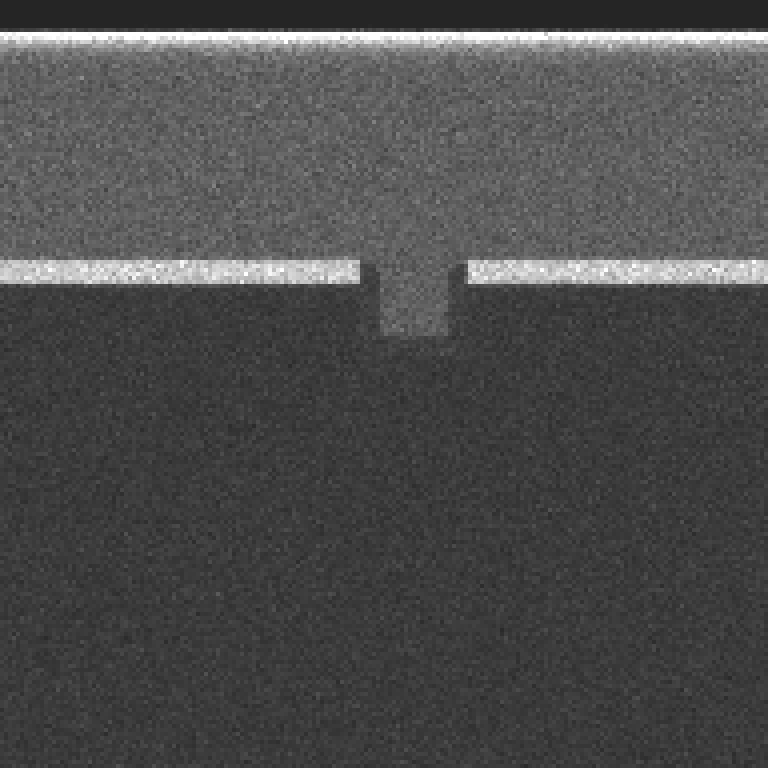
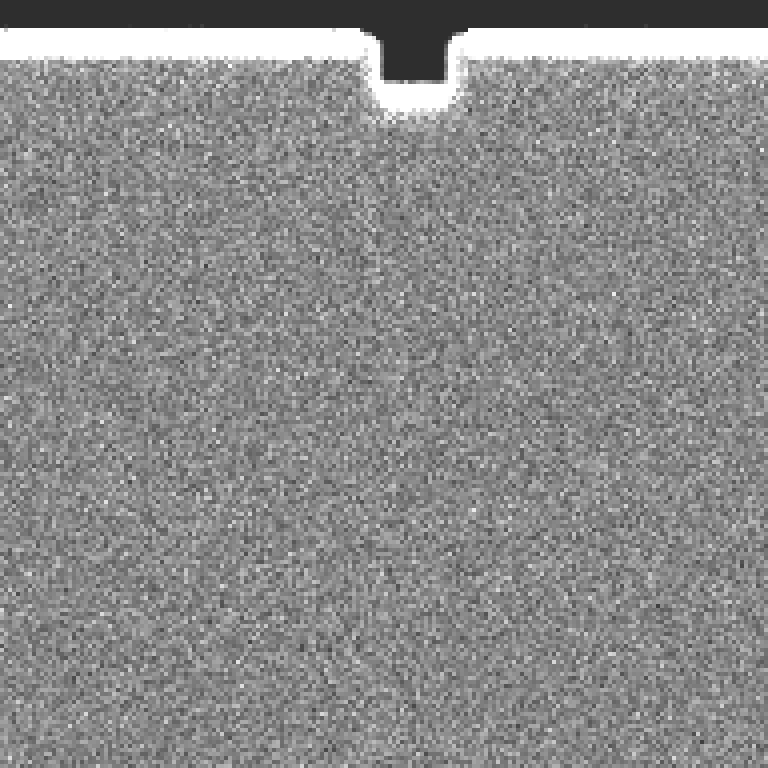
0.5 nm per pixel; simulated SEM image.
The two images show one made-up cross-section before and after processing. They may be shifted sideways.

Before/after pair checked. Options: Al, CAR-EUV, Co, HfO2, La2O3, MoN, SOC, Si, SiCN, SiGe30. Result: removed SOC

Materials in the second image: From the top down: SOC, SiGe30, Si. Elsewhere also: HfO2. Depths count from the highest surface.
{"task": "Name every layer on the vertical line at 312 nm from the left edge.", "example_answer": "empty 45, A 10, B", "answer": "HfO2 12, Si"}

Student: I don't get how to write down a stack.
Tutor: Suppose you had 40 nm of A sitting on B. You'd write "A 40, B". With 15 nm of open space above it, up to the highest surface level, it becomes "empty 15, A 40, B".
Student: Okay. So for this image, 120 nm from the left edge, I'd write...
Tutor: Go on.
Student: HfO2 12, Si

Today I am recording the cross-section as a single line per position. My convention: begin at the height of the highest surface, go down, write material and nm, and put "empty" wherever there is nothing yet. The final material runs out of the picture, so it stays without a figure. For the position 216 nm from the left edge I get empty 26, SOC 12, SiGe30 10, Si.